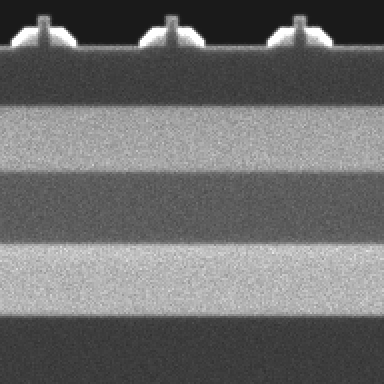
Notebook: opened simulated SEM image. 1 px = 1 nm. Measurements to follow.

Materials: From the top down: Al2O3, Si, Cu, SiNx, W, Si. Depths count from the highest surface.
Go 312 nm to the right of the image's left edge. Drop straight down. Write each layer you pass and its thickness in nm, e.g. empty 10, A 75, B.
empty 12, Al2O3 18, Si 60, Cu 66, SiNx 72, W 72, Si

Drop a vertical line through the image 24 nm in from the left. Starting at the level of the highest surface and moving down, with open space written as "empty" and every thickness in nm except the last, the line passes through empty 12, Al2O3 18, Si 60, Cu 66, SiNx 72, W 72, Si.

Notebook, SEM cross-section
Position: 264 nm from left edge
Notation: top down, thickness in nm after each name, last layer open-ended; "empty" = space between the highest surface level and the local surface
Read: empty 30, Si 60, Cu 66, SiNx 72, W 72, Si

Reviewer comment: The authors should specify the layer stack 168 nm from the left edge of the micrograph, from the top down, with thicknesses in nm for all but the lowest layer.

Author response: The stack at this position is Si 90, Cu 66, SiNx 72, W 72, Si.